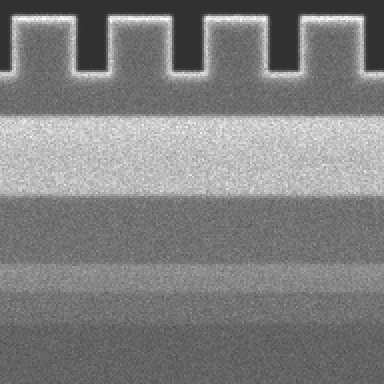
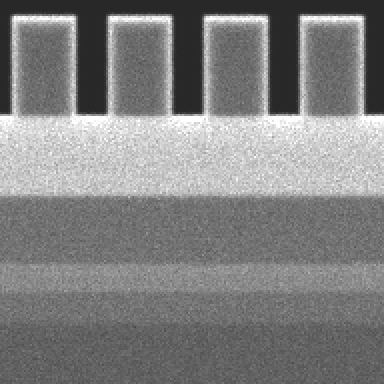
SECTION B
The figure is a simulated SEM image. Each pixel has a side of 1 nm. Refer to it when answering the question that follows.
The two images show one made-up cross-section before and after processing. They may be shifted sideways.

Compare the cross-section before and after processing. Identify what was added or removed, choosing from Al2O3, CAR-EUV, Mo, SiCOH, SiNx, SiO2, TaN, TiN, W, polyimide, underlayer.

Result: underlayer removed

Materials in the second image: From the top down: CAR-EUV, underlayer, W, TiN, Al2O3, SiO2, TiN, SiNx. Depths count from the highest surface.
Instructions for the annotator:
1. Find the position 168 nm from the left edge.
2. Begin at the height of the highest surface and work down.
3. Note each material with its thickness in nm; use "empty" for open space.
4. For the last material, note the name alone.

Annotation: CAR-EUV 56, underlayer 44, W 80, TiN 68, Al2O3 12, SiO2 16, TiN 32, SiNx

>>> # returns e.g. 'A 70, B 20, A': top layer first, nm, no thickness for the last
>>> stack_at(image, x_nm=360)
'CAR-EUV 56, underlayer 44, W 80, TiN 68, Al2O3 12, SiO2 16, TiN 32, SiNx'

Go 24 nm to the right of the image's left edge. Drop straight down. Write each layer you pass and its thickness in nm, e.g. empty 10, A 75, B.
CAR-EUV 56, underlayer 44, W 80, TiN 68, Al2O3 12, SiO2 16, TiN 32, SiNx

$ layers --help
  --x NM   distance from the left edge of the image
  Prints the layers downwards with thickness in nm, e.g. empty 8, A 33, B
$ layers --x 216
CAR-EUV 56, underlayer 44, W 80, TiN 68, Al2O3 12, SiO2 16, TiN 32, SiNx